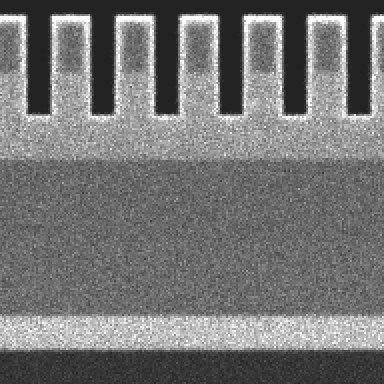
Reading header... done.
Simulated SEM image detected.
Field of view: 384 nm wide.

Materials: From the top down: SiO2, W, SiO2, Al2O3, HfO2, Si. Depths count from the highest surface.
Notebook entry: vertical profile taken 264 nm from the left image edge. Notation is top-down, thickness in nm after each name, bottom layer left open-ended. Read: SiO2 56, W 88, SiO2 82, Al2O3 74, HfO2 34, Si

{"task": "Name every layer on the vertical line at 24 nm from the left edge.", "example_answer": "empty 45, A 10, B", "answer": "SiO2 56, W 88, SiO2 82, Al2O3 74, HfO2 34, Si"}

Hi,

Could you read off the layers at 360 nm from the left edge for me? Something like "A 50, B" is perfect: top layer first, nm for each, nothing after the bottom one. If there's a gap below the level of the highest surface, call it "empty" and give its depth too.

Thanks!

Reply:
empty 100, W 44, SiO2 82, Al2O3 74, HfO2 34, Si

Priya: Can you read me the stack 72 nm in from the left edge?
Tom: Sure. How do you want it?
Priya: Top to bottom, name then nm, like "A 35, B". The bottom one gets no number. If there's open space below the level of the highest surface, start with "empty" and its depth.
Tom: SiO2 56, W 88, SiO2 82, Al2O3 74, HfO2 34, Si